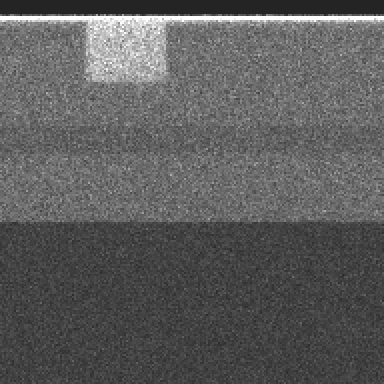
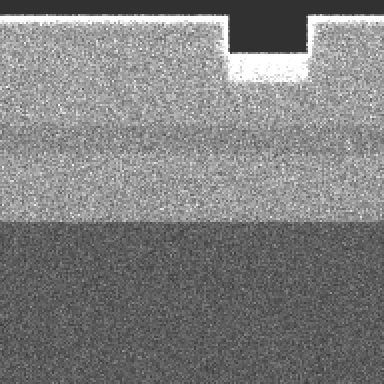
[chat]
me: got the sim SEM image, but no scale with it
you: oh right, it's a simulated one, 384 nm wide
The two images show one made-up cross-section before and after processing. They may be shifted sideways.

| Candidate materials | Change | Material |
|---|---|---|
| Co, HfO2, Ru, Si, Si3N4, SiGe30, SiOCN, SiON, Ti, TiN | removed | Ru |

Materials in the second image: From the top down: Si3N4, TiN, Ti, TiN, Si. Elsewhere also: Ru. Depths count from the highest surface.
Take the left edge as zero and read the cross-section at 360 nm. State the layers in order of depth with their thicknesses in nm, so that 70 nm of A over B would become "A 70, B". Si3N4 24, TiN 86, Ti 28, TiN 68, Si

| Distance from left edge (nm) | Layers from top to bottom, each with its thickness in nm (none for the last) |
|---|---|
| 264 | empty 38, Ru 28, TiN 44, Ti 28, TiN 68, Si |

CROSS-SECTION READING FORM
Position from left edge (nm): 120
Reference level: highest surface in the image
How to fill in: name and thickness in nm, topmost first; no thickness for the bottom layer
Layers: Si3N4 24, TiN 86, Ti 28, TiN 68, Si